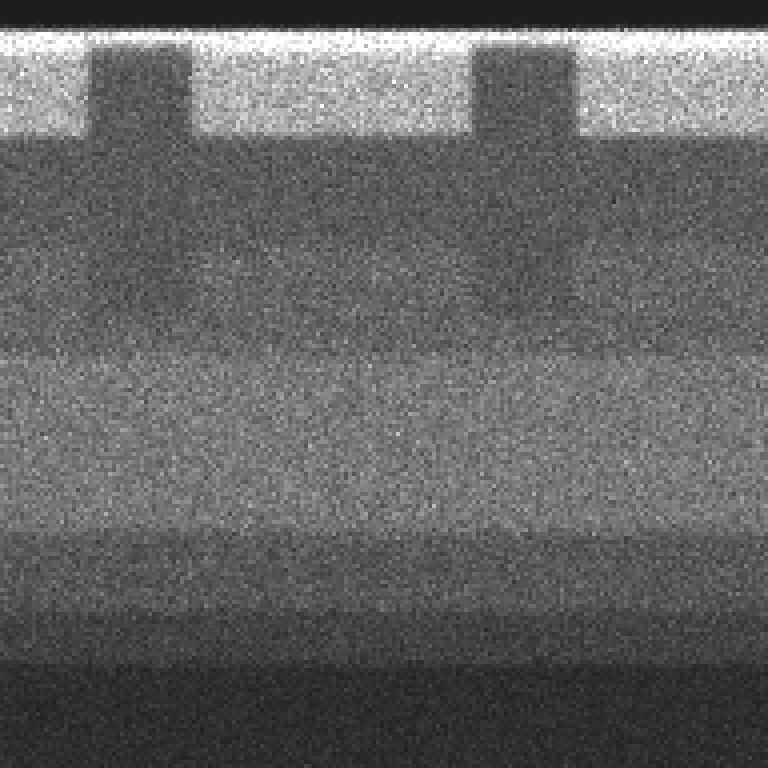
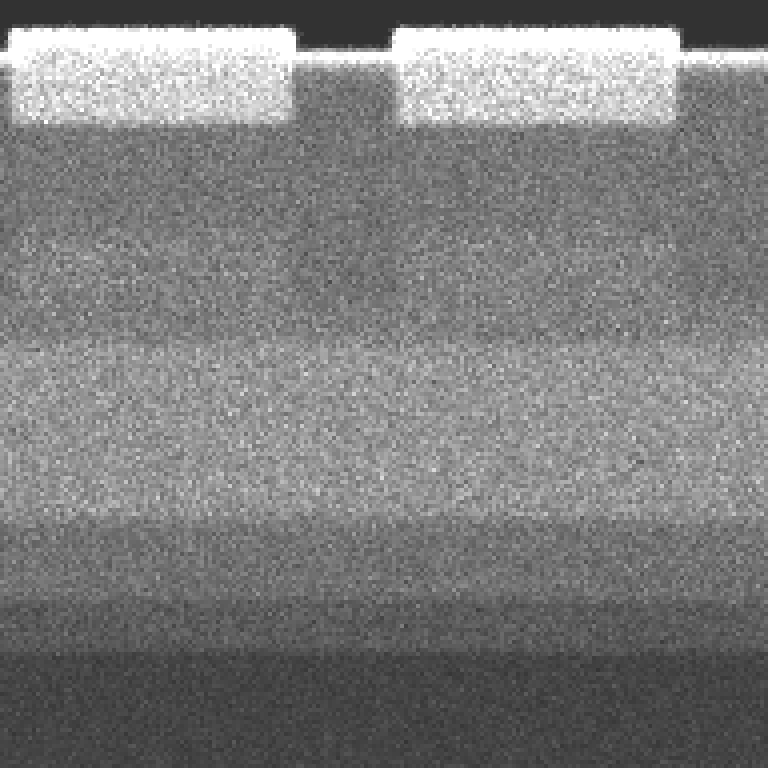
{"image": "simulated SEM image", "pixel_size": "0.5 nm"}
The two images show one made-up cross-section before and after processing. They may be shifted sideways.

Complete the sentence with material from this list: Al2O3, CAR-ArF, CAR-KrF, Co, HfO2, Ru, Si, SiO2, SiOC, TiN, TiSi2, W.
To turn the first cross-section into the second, SiO2 must be removed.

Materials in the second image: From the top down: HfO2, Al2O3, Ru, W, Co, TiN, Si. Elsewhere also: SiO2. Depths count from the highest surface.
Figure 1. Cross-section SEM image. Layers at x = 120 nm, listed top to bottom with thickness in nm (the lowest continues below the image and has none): HfO2 46, Al2O3 54, Ru 56, W 88, Co 40, TiN 26, Si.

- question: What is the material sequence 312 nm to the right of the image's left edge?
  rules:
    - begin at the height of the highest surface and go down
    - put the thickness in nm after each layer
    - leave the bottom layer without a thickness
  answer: HfO2 46, Al2O3 54, Ru 56, W 88, Co 40, TiN 26, Si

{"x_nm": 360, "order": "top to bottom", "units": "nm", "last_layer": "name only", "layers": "empty 10, SiO2 126, Ru 20, W 88, Co 40, TiN 26, Si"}